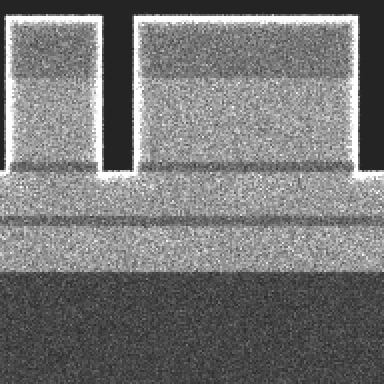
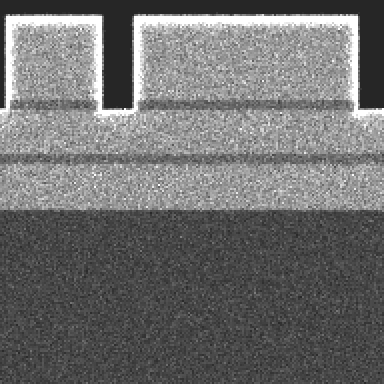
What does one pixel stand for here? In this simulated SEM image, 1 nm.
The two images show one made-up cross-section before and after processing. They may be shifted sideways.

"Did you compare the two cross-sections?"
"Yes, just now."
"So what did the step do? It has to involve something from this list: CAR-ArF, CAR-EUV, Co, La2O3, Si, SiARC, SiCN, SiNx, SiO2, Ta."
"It removed SiARC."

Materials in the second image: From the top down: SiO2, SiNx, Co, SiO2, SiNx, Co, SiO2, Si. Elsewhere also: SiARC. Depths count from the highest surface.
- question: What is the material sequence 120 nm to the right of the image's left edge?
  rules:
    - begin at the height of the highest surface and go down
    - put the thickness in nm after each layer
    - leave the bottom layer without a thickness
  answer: empty 94, Co 24, SiO2 20, SiNx 10, SiO2 46, Si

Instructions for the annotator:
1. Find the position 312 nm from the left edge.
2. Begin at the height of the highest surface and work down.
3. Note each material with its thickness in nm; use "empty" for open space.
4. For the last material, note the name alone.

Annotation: SiO2 84, SiNx 10, SiO2 44, SiNx 10, SiO2 46, Si